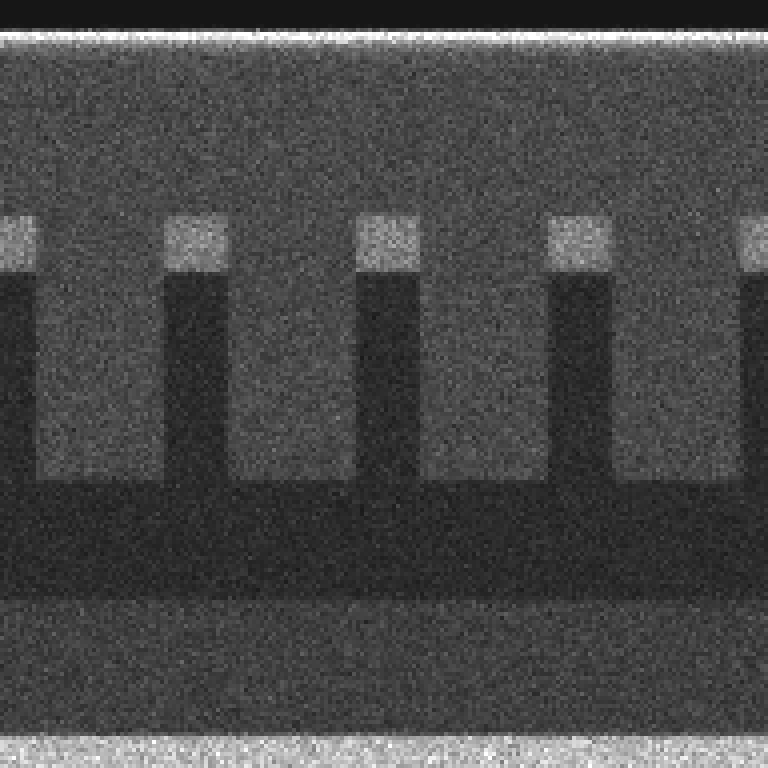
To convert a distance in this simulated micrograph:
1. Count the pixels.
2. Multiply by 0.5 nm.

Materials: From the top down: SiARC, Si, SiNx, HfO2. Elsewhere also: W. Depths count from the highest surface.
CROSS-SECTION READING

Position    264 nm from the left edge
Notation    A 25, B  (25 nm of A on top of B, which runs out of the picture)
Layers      SiARC 224, Si 60, SiNx 68, HfO2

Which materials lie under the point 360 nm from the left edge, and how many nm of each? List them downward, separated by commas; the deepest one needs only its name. SiARC 224, Si 60, SiNx 68, HfO2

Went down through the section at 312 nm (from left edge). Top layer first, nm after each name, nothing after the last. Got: SiARC 224, Si 60, SiNx 68, HfO2